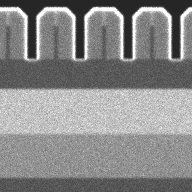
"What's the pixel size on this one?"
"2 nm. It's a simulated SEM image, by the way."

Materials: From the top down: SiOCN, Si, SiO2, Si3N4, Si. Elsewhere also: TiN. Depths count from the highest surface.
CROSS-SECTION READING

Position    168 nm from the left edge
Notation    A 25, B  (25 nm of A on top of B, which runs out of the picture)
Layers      empty 102, Si 60, SiO2 90, Si3N4 88, Si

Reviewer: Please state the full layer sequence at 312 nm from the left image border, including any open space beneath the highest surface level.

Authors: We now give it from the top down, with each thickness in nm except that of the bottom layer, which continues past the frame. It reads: SiOCN 102, Si 60, SiO2 90, Si3N4 88, Si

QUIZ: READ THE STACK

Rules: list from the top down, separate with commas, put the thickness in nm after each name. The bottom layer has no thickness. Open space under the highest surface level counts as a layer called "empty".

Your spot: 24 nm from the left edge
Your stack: SiOCN 102, Si 60, SiO2 90, Si3N4 88, Si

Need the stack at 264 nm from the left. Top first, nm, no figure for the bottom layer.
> empty 102, Si 60, SiO2 90, Si3N4 88, Si